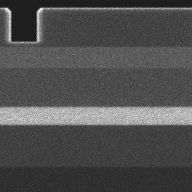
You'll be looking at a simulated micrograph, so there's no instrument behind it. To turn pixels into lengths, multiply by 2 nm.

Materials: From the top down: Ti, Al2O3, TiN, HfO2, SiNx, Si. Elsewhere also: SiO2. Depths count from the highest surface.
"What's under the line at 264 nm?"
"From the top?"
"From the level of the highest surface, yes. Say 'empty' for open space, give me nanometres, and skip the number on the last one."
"Ti 78, Al2O3 42, TiN 78, HfO2 36, SiNx 84, Si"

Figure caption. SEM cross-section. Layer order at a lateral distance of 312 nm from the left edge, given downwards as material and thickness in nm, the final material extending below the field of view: Ti 78, Al2O3 42, TiN 78, HfO2 36, SiNx 84, Si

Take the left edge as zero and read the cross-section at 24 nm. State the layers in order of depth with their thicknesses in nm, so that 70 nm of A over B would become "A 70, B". empty 68, Ti 10, Al2O3 42, TiN 78, HfO2 36, SiNx 84, Si